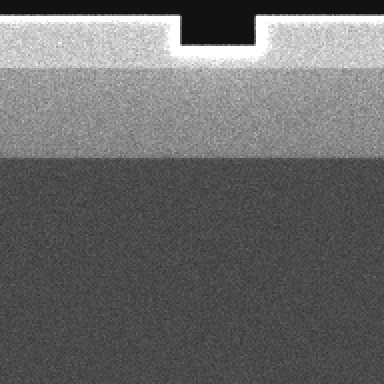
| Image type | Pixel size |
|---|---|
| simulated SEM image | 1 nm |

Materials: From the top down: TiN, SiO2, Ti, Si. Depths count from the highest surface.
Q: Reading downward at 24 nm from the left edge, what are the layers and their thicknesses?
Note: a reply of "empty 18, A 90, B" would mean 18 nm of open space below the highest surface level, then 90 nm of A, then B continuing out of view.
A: TiN 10, SiO2 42, Ti 90, Si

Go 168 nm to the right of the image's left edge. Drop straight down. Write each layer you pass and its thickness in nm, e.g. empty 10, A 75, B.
TiN 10, SiO2 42, Ti 90, Si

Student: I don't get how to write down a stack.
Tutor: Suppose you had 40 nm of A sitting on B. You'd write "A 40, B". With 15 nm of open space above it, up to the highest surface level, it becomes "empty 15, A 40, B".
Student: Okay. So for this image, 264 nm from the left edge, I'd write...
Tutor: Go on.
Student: TiN 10, SiO2 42, Ti 90, Si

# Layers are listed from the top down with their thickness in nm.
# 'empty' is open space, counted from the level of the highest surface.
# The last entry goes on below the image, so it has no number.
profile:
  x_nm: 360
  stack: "TiN 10, SiO2 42, Ti 90, Si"